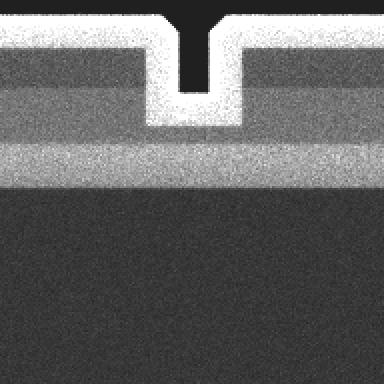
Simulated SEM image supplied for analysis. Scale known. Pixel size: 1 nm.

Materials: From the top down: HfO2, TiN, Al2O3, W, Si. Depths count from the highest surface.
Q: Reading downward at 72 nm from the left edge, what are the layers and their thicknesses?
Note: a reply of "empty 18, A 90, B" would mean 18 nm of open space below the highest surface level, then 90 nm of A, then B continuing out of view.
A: HfO2 32, TiN 40, Al2O3 56, W 44, Si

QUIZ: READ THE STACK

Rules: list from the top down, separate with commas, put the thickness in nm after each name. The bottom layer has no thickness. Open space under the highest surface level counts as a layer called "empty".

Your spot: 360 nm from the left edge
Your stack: HfO2 32, TiN 40, Al2O3 56, W 44, Si